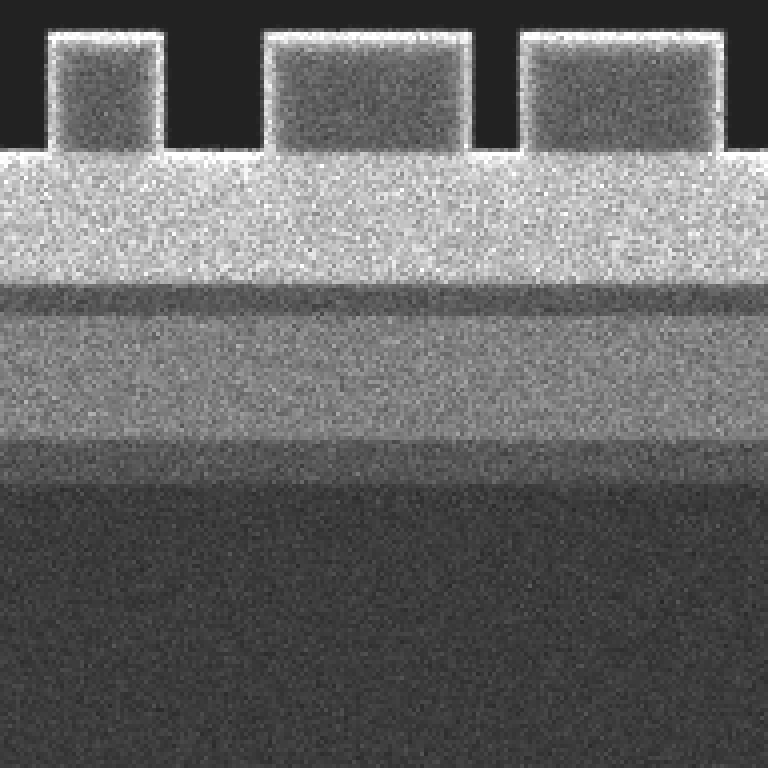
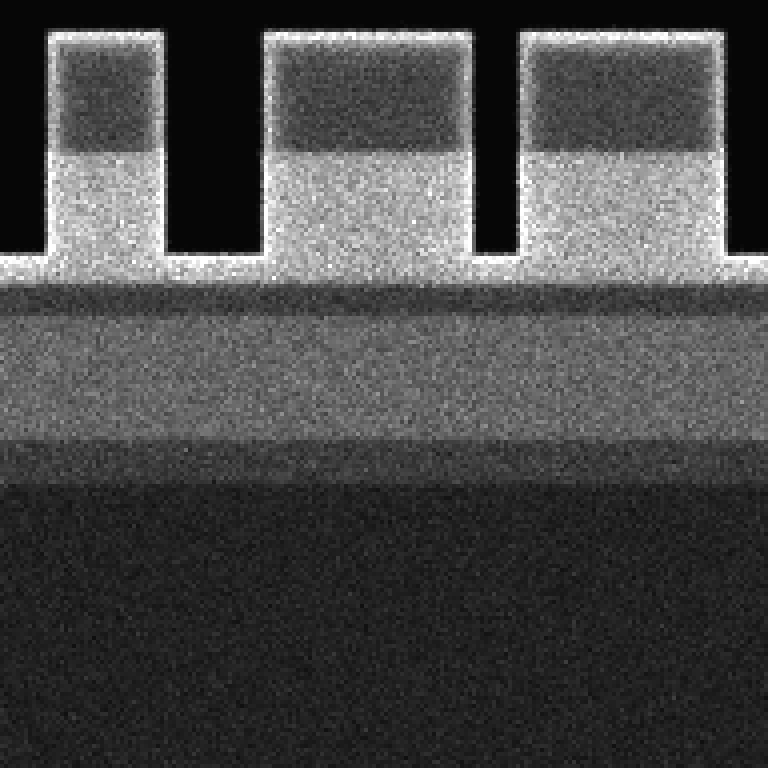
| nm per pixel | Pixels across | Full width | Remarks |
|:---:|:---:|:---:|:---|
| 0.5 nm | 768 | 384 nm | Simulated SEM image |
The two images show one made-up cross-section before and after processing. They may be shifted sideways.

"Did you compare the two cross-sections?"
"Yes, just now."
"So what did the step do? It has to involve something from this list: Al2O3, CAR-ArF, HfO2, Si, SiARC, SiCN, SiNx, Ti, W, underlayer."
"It removed W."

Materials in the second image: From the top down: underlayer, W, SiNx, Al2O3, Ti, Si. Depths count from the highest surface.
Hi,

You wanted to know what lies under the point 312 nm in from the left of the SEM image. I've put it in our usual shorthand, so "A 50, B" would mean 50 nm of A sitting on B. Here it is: underlayer 60, W 66, SiNx 16, Al2O3 62, Ti 22, Si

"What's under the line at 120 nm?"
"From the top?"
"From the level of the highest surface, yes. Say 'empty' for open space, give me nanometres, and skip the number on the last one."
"empty 112, W 14, SiNx 16, Al2O3 62, Ti 22, Si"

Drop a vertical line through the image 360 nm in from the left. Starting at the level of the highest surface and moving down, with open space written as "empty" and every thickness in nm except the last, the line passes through underlayer 60, W 66, SiNx 16, Al2O3 62, Ti 22, Si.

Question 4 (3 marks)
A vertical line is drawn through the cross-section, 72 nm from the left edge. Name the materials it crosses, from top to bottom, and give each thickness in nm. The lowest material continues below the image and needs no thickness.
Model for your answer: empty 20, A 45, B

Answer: underlayer 60, W 66, SiNx 16, Al2O3 62, Ti 22, Si